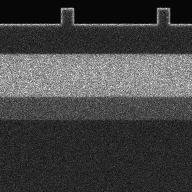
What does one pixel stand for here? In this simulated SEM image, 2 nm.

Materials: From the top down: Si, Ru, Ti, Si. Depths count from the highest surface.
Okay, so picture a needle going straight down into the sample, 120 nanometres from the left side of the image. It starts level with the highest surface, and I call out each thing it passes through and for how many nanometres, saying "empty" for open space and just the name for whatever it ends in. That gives empty 32, Si 60, Ru 86, Ti 46, Si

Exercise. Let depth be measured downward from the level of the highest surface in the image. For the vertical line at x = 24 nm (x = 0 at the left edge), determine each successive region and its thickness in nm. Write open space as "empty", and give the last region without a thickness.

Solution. empty 32, Si 60, Ru 86, Ti 46, Si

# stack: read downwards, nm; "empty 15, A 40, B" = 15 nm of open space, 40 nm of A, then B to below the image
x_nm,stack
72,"empty 32, Si 60, Ru 86, Ti 46, Si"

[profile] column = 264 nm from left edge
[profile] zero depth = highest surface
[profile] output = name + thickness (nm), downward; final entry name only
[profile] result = empty 32, Si 60, Ru 86, Ti 46, Si